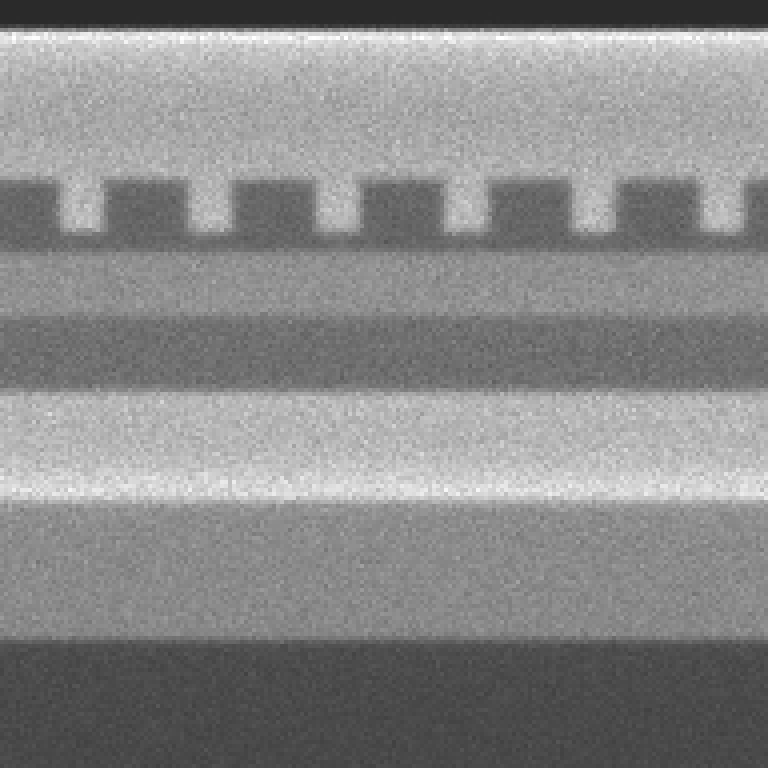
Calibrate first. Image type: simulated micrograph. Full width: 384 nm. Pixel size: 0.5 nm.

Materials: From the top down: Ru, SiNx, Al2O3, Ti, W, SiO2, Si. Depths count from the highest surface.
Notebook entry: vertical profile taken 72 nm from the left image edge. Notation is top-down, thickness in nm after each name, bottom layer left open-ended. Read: Ru 74, SiNx 36, Al2O3 32, Ti 38, W 54, SiO2 70, Si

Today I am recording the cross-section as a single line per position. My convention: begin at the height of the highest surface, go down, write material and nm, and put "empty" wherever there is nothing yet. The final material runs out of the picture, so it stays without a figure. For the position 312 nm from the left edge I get Ru 74, SiNx 36, Al2O3 32, Ti 38, W 54, SiO2 70, Si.